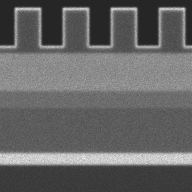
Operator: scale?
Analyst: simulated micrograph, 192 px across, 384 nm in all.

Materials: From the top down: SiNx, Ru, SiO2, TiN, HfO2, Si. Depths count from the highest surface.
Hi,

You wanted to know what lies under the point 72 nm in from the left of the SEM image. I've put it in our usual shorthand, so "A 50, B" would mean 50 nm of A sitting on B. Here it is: SiNx 90, Ru 76, SiO2 34, TiN 90, HfO2 24, Si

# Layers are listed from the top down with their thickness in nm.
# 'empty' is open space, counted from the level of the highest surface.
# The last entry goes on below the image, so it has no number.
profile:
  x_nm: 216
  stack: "empty 76, SiNx 14, Ru 76, SiO2 34, TiN 90, HfO2 24, Si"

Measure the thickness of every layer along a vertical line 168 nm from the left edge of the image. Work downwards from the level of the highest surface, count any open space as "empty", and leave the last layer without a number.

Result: SiNx 90, Ru 76, SiO2 34, TiN 90, HfO2 24, Si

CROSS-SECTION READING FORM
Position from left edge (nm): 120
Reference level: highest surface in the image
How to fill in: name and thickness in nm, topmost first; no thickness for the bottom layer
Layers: empty 76, SiNx 14, Ru 76, SiO2 34, TiN 90, HfO2 24, Si